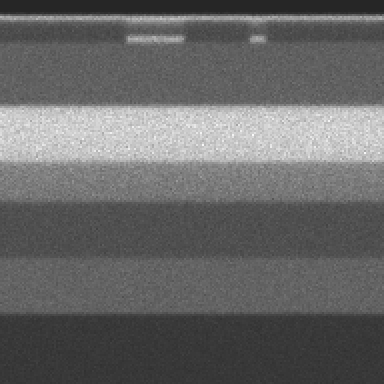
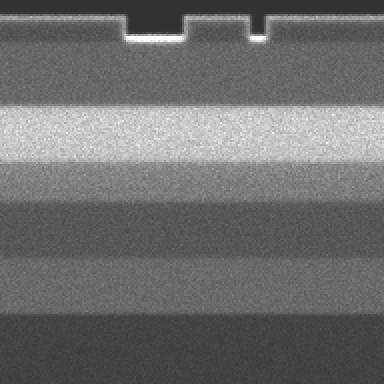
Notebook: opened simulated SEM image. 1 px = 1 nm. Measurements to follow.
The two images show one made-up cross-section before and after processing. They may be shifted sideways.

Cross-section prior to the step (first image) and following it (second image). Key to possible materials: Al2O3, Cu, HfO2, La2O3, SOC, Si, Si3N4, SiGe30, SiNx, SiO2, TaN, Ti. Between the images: SOC was removed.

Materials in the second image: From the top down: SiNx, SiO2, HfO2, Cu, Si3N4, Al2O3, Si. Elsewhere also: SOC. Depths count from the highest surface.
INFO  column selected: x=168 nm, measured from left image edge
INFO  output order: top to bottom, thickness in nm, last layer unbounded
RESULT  empty 20, HfO2 6, SiO2 64, HfO2 56, Cu 40, Si3N4 56, Al2O3 56, Si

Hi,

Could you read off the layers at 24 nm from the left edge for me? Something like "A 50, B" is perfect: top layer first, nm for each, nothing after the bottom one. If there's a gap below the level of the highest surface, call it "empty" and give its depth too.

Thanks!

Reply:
SiNx 26, SiO2 64, HfO2 56, Cu 40, Si3N4 56, Al2O3 56, Si